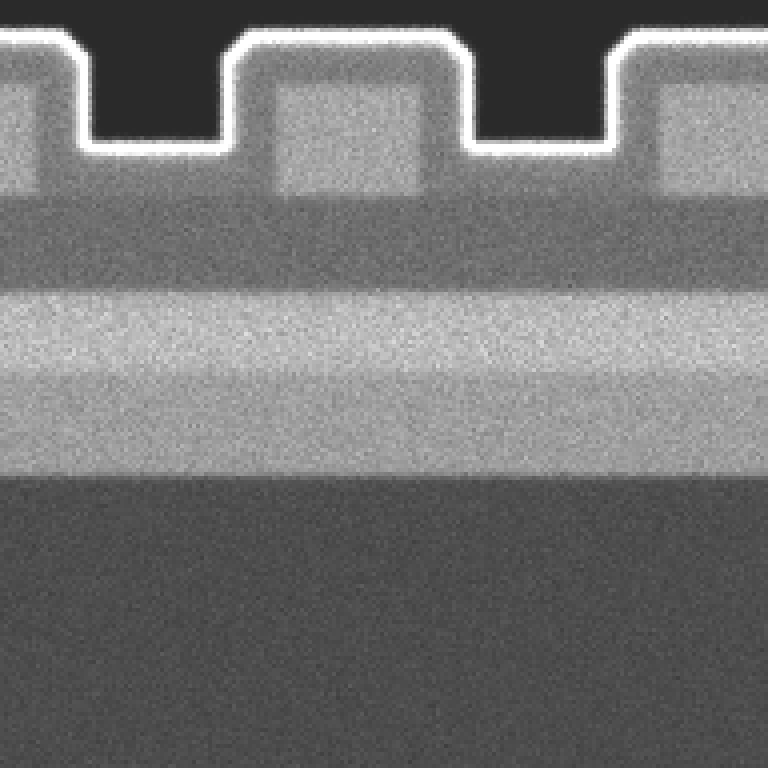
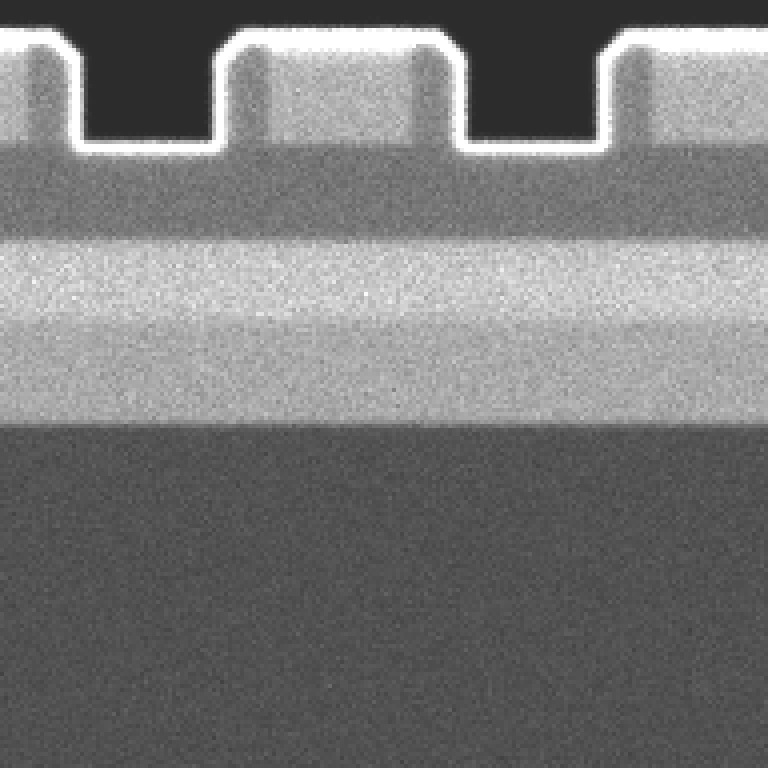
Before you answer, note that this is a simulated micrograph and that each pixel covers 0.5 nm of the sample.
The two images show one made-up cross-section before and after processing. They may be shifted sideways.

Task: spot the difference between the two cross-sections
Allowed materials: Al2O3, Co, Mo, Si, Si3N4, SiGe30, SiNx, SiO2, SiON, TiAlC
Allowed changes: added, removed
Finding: removed Si3N4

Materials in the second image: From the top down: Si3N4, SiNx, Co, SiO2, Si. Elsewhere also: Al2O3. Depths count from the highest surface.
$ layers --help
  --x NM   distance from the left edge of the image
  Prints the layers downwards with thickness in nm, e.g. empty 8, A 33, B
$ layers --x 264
empty 56, SiNx 48, Co 40, SiO2 52, Si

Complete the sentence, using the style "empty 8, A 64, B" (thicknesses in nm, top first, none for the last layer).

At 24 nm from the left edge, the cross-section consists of Si3N4 56, SiNx 48, Co 40, SiO2 52, Si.